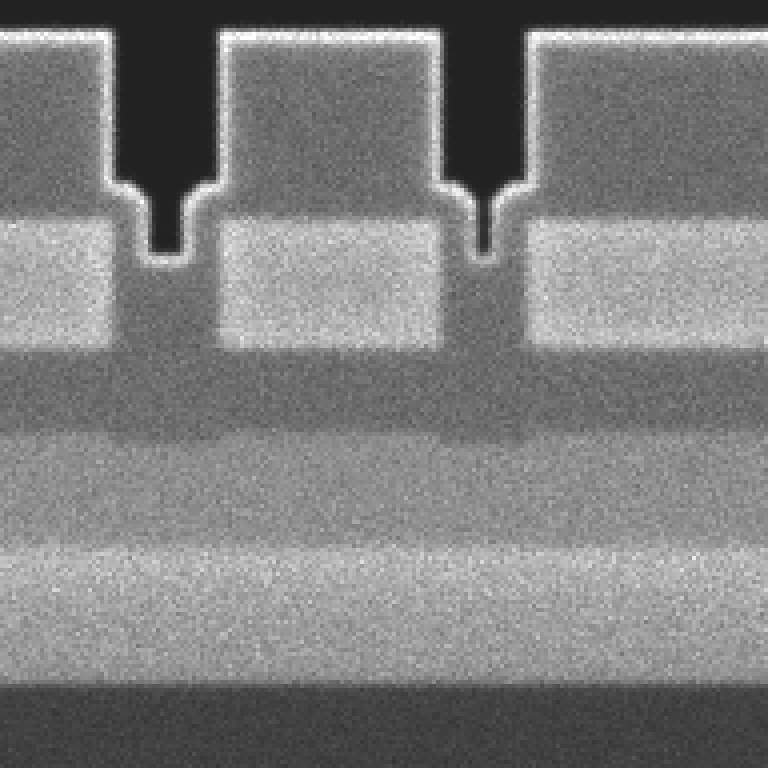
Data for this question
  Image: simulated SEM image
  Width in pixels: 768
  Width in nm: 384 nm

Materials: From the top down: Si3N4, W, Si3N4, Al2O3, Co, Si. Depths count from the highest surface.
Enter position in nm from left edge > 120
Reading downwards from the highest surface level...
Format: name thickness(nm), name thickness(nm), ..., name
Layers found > Si3N4 94, W 64, Si3N4 42, Al2O3 58, Co 68, Si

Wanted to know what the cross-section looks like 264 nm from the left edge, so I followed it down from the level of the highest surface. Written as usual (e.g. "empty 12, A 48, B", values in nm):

Si3N4 94, W 64, Si3N4 42, Al2O3 58, Co 68, Si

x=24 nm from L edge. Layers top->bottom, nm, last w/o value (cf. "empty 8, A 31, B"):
Si3N4 94, W 64, Si3N4 42, Al2O3 58, Co 68, Si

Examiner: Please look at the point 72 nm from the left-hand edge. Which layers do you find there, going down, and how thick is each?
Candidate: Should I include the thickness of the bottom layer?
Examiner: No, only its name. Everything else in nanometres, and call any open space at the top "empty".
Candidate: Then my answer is empty 84, Si3N4 122, Al2O3 52, Co 68, Si